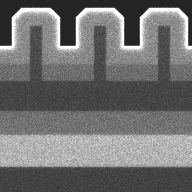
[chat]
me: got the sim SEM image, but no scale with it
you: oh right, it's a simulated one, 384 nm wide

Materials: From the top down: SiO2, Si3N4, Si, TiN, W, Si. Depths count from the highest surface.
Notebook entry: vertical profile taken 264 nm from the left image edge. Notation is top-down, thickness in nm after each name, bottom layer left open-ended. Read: empty 76, SiO2 36, Si3N4 34, Si 60, TiN 48, W 64, Si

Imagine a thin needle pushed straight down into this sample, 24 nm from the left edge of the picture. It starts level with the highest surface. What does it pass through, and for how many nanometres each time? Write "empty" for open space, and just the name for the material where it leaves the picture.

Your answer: empty 18, SiO2 94, Si3N4 34, Si 60, TiN 48, W 64, Si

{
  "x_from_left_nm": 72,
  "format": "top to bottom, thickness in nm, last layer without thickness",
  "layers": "SiO2 36, Si 170, TiN 48, W 64, Si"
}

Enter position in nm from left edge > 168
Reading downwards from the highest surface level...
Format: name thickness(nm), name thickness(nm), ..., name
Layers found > empty 2, SiO2 110, Si3N4 34, Si 60, TiN 48, W 64, Si